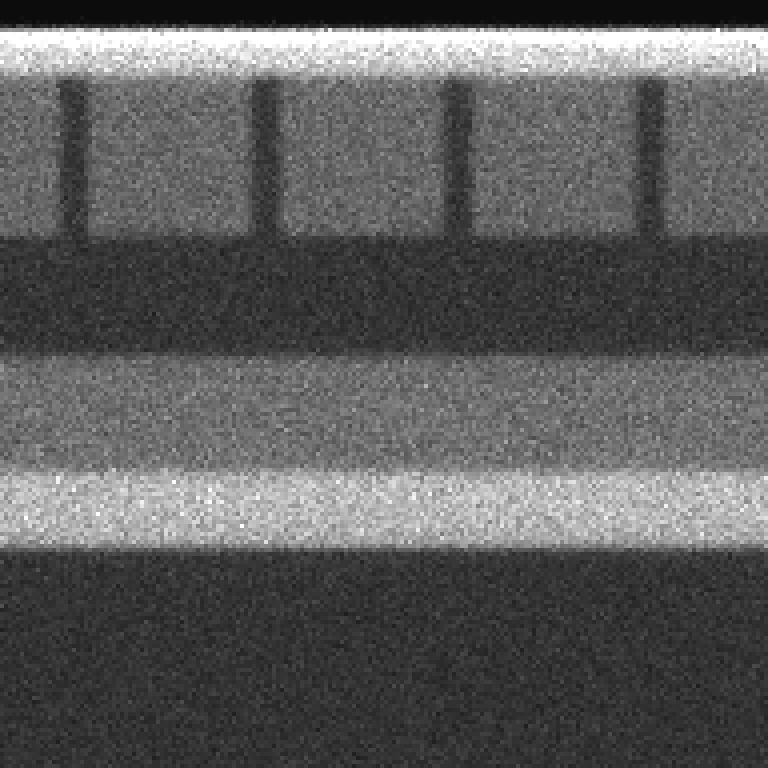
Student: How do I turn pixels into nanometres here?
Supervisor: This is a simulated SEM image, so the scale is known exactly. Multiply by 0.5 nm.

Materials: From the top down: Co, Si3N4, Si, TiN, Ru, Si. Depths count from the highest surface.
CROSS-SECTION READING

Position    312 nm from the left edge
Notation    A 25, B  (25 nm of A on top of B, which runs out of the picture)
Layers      Co 22, Si3N4 80, Si 60, TiN 58, Ru 38, Si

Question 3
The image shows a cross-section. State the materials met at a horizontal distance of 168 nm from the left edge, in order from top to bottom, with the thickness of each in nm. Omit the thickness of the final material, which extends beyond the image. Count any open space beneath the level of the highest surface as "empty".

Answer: Co 22, Si3N4 80, Si 60, TiN 58, Ru 38, Si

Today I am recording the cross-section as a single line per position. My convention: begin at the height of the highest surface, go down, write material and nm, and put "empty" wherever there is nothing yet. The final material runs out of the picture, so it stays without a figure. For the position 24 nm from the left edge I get Co 22, Si3N4 80, Si 60, TiN 58, Ru 38, Si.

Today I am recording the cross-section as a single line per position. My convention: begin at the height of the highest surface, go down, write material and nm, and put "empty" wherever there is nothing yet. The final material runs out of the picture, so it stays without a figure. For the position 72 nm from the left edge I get Co 22, Si3N4 80, Si 60, TiN 58, Ru 38, Si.